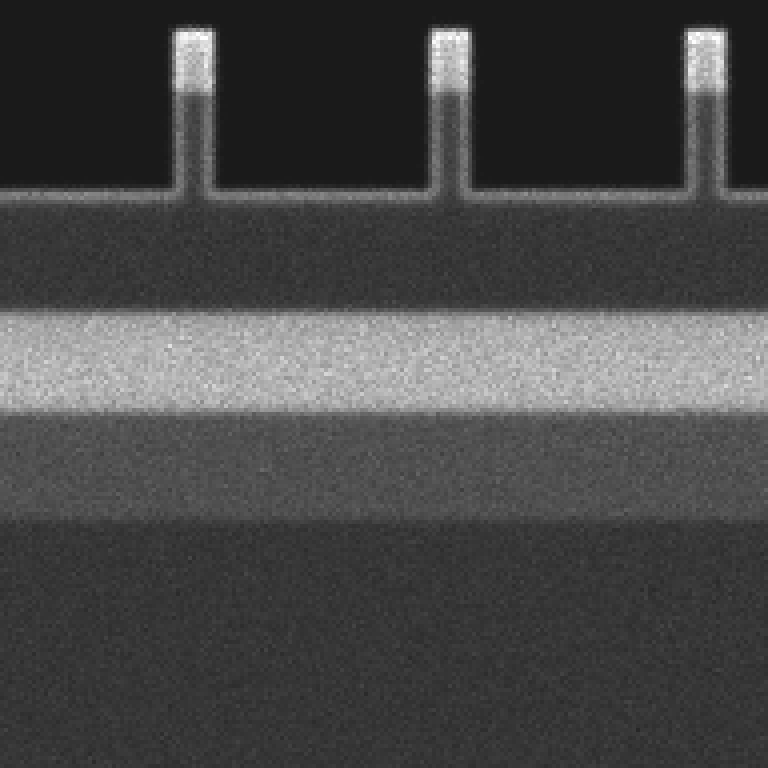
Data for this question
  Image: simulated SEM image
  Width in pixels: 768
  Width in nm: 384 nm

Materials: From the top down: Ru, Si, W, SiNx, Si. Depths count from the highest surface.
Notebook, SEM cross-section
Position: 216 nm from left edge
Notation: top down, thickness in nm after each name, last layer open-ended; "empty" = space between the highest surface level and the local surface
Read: Ru 30, Si 110, W 50, SiNx 54, Si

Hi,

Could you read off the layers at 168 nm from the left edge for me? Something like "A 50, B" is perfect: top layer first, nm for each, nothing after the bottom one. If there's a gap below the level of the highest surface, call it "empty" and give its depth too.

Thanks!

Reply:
empty 80, Si 60, W 50, SiNx 54, Si